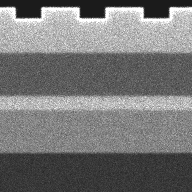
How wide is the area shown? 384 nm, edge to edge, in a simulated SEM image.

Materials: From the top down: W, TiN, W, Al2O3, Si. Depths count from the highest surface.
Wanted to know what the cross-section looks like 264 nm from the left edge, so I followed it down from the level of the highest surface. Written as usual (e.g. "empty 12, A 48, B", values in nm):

W 90, TiN 86, W 28, Al2O3 86, Si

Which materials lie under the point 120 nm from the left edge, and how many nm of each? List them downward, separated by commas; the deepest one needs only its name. W 90, TiN 86, W 28, Al2O3 86, Si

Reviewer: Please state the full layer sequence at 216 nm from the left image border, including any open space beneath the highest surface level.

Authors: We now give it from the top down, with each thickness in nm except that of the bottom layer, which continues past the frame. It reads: W 90, TiN 86, W 28, Al2O3 86, Si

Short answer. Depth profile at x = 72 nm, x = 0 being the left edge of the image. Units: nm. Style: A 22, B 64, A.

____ empty 22, W 68, TiN 86, W 28, Al2O3 86, Si